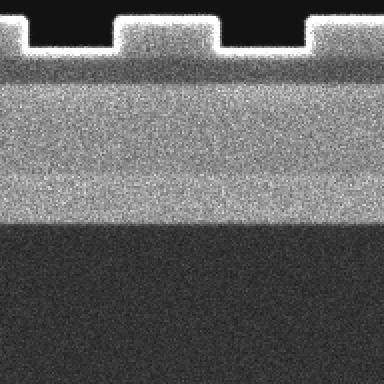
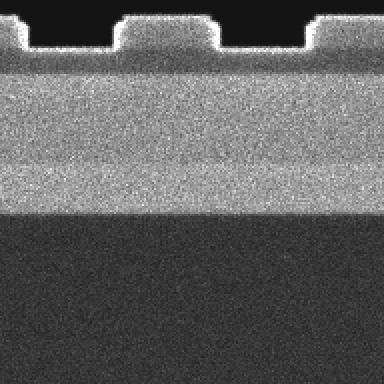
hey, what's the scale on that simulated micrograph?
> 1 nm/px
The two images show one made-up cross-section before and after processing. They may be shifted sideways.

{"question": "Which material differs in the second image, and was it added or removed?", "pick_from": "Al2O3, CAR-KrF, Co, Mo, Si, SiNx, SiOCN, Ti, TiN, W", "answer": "Al2O3, removed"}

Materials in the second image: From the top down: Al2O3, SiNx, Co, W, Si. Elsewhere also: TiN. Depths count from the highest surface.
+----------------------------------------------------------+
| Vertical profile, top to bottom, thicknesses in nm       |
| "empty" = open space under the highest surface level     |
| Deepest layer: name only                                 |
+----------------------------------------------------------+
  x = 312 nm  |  empty 6, Al2O3 26, SiNx 26, Co 90, W 50, Si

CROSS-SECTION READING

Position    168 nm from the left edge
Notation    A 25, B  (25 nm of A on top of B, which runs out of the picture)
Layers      TiN 32, SiNx 26, Co 90, W 50, Si